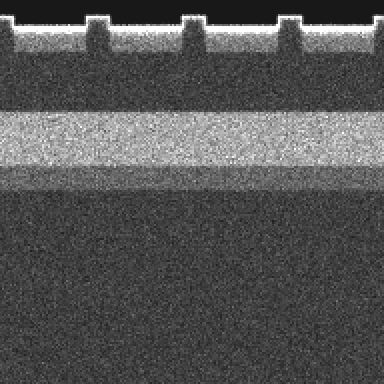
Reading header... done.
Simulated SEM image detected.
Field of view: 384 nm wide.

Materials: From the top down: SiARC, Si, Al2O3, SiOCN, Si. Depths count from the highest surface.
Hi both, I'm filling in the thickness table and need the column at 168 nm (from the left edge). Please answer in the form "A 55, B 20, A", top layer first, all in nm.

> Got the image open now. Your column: empty 10, SiARC 26, Si 60, Al2O3 54, SiOCN 24, Si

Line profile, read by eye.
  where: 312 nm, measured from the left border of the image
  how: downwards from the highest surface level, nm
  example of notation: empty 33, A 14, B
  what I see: empty 10, SiARC 26, Si 60, Al2O3 54, SiOCN 24, Si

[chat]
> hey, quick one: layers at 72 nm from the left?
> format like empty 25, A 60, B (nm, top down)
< empty 10, SiARC 26, Si 60, Al2O3 54, SiOCN 24, Si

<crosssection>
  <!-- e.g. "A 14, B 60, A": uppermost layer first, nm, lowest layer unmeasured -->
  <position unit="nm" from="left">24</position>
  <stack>empty 10, SiARC 26, Si 60, Al2O3 54, SiOCN 24, Si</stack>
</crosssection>